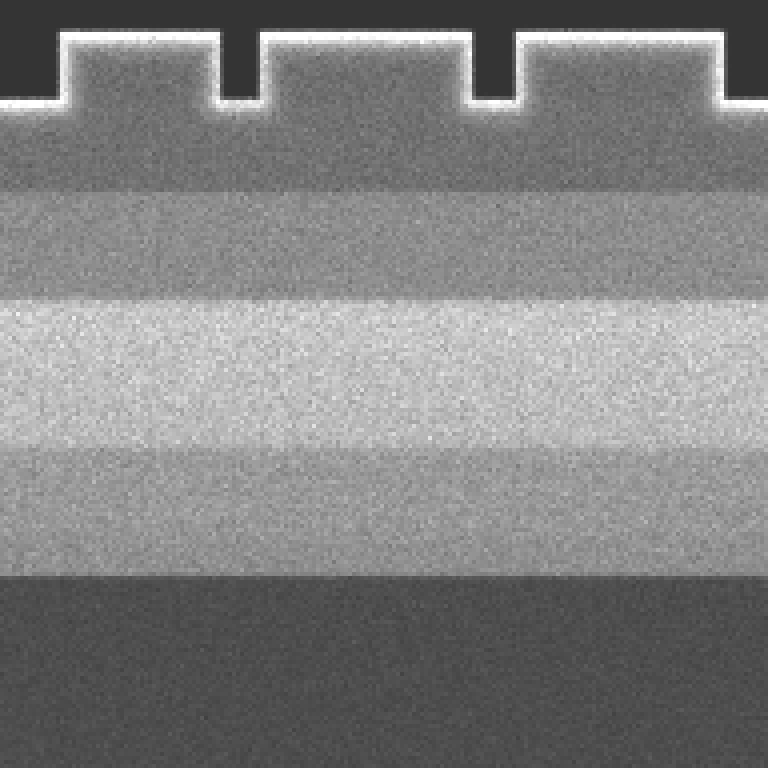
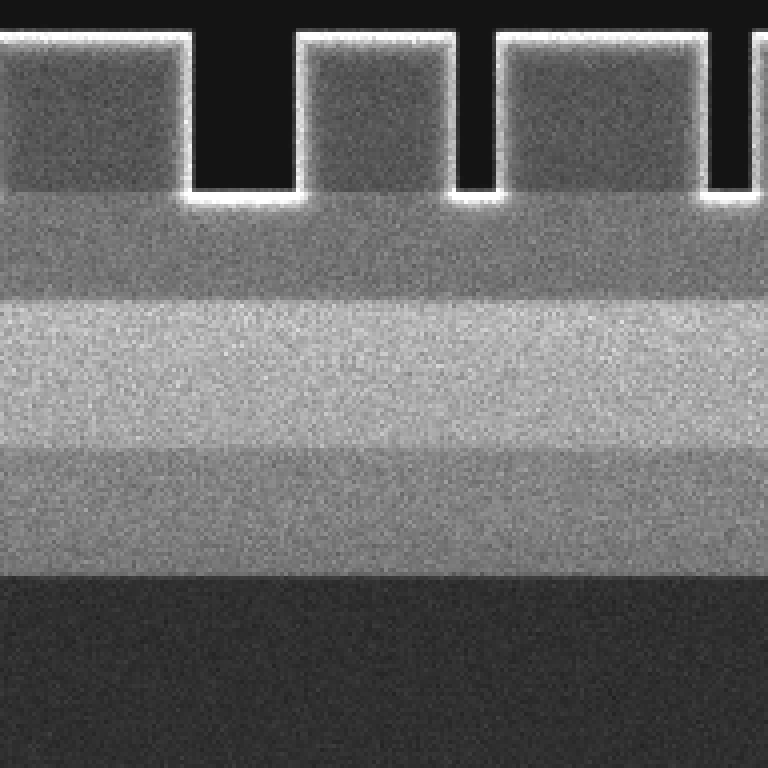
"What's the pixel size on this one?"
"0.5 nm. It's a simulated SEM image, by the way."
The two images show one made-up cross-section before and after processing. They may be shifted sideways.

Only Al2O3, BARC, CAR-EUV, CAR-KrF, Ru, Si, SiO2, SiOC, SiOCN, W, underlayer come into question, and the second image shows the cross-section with underlayer removed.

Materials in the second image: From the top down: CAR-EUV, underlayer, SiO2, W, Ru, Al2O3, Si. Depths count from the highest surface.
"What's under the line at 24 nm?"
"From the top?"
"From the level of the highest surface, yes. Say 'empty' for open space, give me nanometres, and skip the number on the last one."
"CAR-EUV 34, underlayer 46, SiO2 54, W 74, Ru 46, Al2O3 18, Si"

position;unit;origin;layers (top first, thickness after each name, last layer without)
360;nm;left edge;empty 80, SiO2 54, W 74, Ru 46, Al2O3 18, Si